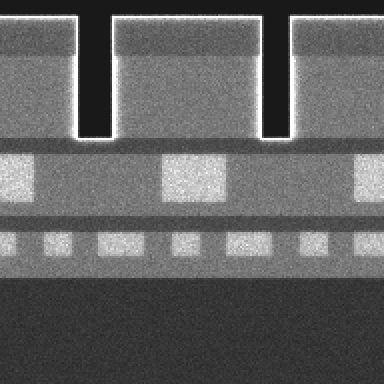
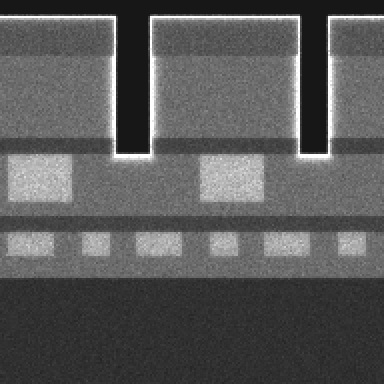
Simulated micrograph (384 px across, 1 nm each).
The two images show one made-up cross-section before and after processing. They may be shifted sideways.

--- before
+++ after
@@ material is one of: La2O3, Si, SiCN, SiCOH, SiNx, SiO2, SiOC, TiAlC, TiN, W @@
SiCN removed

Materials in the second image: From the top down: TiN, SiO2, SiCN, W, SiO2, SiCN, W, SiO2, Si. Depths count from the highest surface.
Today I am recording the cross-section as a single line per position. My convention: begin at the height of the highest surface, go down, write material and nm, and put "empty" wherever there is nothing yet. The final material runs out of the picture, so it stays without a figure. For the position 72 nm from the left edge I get TiN 40, SiO2 82, SiCN 16, SiO2 62, SiCN 16, SiO2 46, Si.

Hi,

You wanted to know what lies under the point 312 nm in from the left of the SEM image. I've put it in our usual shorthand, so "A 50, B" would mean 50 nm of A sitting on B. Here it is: empty 138, SiO2 62, SiCN 16, SiO2 46, Si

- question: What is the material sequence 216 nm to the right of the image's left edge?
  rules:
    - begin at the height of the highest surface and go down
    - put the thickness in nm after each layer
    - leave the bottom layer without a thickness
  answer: TiN 40, SiO2 82, SiCN 16, W 48, SiO2 14, SiCN 16, W 24, SiO2 22, Si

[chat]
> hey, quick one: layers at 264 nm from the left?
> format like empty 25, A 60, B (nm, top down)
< TiN 40, SiO2 82, SiCN 16, SiO2 62, SiCN 16, W 24, SiO2 22, Si